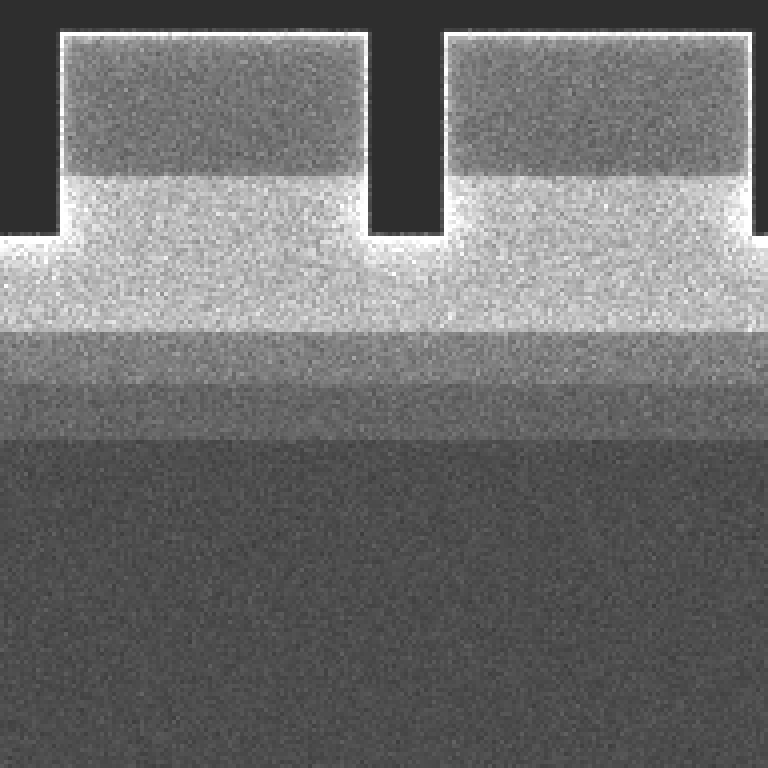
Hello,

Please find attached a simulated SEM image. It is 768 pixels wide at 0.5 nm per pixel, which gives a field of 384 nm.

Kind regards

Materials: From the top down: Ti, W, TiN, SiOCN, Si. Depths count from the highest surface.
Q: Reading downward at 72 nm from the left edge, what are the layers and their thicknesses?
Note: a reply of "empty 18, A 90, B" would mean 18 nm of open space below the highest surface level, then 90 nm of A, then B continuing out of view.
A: Ti 72, W 78, TiN 26, SiOCN 28, Si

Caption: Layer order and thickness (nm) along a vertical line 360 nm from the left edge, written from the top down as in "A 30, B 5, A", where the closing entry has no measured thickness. Ti 72, W 78, TiN 26, SiOCN 28, Si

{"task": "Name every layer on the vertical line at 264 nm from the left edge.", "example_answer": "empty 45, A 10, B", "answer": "Ti 72, W 78, TiN 26, SiOCN 28, Si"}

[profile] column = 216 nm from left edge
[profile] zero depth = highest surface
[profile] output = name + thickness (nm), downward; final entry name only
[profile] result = empty 102, W 48, TiN 26, SiOCN 28, Si